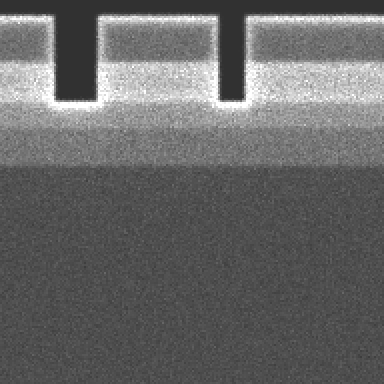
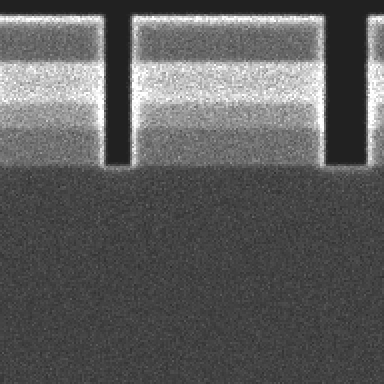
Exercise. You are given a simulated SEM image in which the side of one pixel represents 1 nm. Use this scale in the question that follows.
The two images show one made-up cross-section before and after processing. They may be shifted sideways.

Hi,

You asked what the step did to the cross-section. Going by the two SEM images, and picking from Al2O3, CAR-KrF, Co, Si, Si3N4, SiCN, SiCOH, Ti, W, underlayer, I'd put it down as Al2O3 and Si3N4, removed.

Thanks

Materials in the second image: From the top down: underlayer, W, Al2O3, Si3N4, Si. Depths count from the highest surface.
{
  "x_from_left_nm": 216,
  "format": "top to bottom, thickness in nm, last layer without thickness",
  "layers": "underlayer 46, W 40, Al2O3 26, Si3N4 38, Si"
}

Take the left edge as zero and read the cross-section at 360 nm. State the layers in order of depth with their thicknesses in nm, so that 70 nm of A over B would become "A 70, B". empty 150, Si